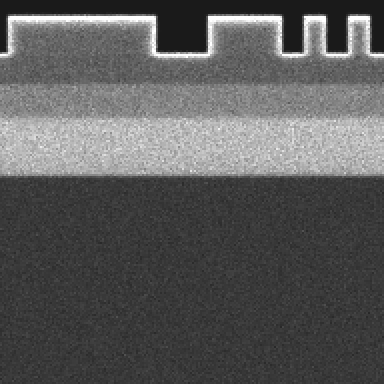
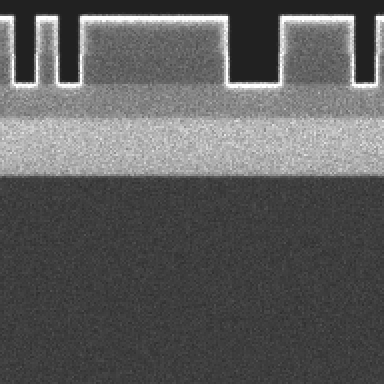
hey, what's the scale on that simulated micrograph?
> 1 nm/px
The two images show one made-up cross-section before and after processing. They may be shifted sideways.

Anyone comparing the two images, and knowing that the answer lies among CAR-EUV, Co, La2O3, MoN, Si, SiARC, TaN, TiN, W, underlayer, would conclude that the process removed TiN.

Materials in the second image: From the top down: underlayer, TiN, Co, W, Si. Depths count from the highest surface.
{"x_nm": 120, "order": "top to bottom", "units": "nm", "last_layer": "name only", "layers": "underlayer 38, TiN 30, Co 34, W 58, Si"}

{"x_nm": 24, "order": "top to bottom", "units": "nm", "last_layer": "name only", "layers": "empty 68, Co 34, W 58, Si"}